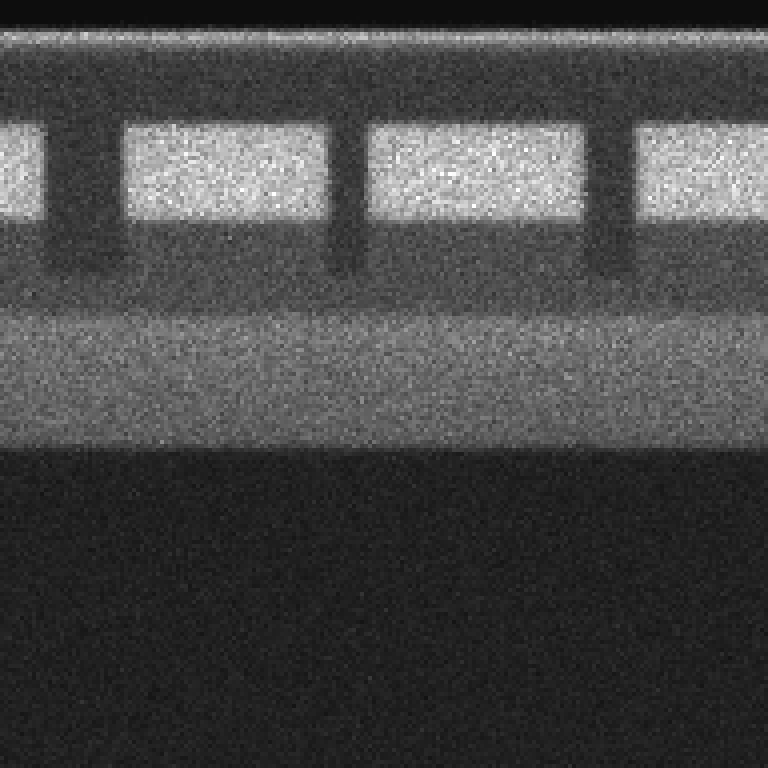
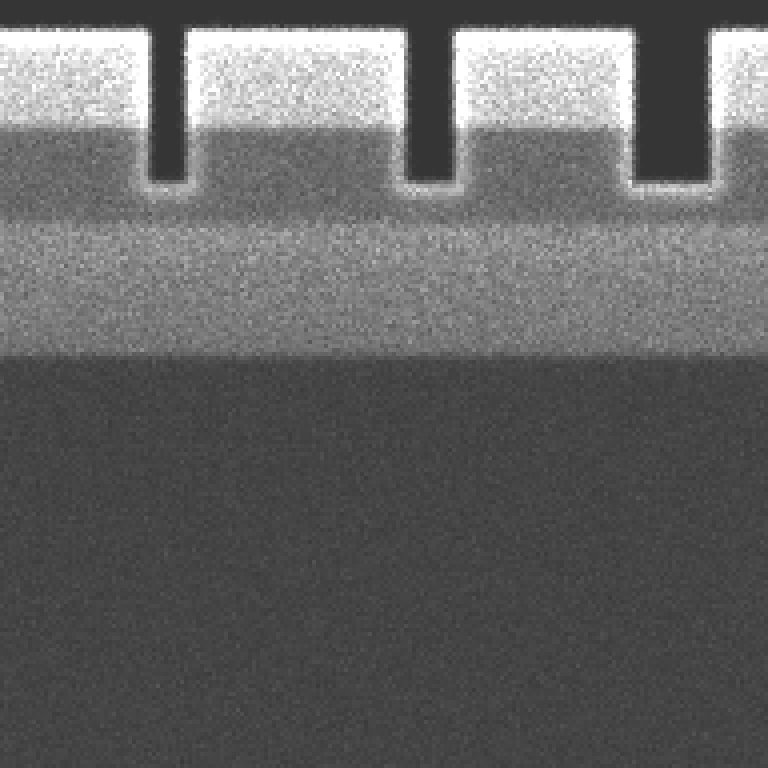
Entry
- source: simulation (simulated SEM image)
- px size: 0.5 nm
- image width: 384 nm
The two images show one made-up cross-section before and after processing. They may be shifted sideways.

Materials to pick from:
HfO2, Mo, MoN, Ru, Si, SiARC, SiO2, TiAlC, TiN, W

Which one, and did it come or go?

SiARC - removed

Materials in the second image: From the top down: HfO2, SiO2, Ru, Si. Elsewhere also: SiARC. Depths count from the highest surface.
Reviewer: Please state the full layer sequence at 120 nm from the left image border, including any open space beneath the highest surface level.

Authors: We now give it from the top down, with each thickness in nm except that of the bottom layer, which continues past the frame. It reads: HfO2 48, SiO2 48, Ru 66, Si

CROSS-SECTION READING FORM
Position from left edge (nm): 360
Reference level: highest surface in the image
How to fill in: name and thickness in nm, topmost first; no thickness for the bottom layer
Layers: HfO2 48, SiO2 48, Ru 66, Si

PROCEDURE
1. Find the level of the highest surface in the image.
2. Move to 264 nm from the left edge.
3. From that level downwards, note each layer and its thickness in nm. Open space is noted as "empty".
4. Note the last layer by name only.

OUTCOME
HfO2 48, SiO2 48, Ru 66, Si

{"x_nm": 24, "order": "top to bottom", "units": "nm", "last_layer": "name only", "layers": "HfO2 48, SiO2 48, Ru 66, Si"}